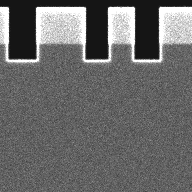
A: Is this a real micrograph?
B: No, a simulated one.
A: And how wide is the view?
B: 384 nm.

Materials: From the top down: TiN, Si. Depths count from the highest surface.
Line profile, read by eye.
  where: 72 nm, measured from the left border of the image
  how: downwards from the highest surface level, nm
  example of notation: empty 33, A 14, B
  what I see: empty 104, Si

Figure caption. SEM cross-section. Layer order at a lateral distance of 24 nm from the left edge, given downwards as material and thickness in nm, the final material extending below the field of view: empty 104, Si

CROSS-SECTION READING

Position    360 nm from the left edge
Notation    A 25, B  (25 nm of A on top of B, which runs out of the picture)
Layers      TiN 72, Si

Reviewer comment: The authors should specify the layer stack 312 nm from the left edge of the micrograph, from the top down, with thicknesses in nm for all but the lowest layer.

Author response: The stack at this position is empty 104, Si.